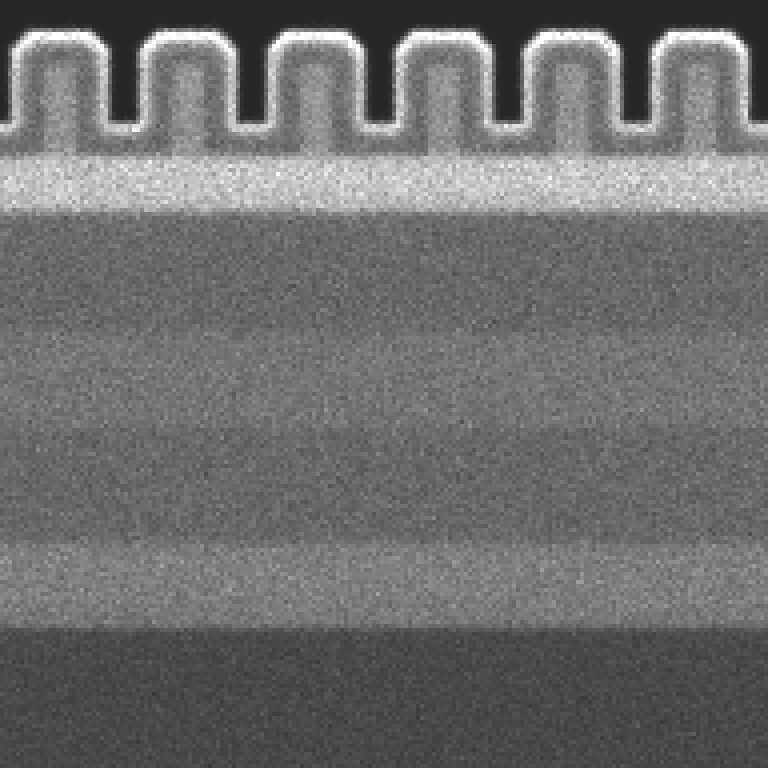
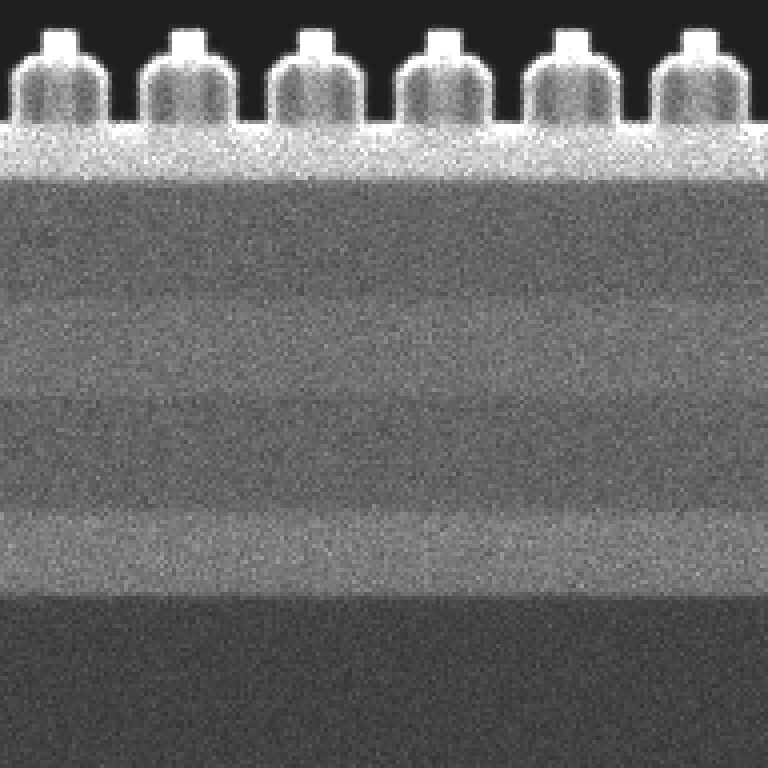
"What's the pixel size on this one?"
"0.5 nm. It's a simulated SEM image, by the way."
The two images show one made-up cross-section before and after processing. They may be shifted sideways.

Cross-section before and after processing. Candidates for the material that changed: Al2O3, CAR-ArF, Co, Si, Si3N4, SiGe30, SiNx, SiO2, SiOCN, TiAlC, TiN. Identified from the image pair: SiOCN (removed).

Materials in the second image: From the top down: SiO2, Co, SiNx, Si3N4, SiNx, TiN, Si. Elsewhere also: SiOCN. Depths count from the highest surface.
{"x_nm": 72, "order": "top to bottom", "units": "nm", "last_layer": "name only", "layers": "empty 18, SiOCN 28, Co 28, SiNx 60, Si3N4 48, SiNx 58, TiN 42, Si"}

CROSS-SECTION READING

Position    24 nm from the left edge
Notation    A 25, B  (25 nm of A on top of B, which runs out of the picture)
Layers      SiO2 46, Co 28, SiNx 60, Si3N4 48, SiNx 58, TiN 42, Si